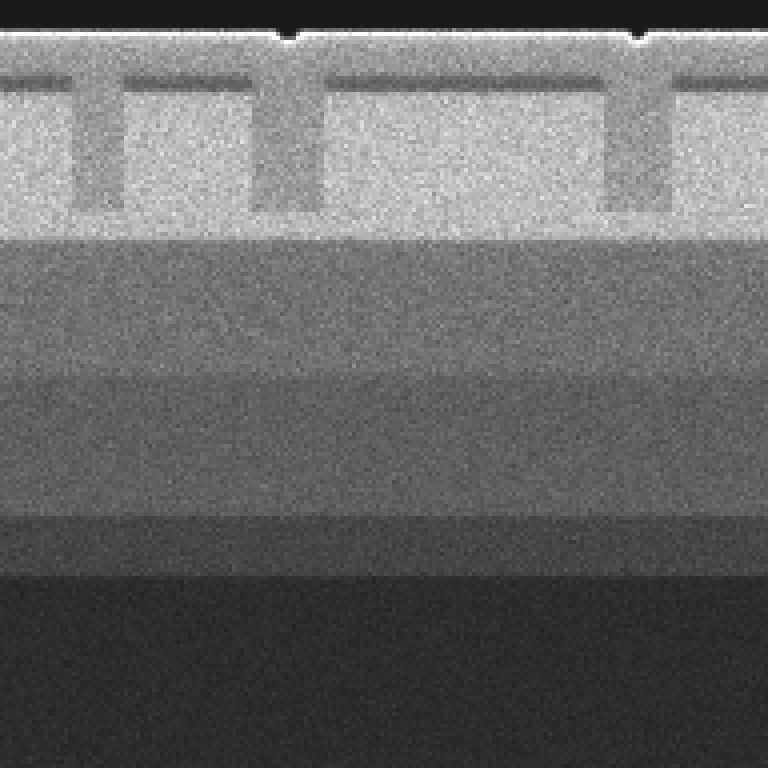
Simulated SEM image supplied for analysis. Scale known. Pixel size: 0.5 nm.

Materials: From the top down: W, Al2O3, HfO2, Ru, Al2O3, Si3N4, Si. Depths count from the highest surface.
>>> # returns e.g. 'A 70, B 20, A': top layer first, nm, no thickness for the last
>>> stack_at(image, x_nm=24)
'W 22, Al2O3 8, HfO2 74, Ru 68, Al2O3 70, Si3N4 30, Si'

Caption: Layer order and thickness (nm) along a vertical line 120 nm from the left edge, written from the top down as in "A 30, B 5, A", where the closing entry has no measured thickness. W 22, Al2O3 8, HfO2 74, Ru 68, Al2O3 70, Si3N4 30, Si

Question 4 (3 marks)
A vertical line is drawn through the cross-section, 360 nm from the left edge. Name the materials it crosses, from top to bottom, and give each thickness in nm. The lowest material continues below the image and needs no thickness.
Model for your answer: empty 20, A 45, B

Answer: W 22, Al2O3 8, HfO2 74, Ru 68, Al2O3 70, Si3N4 30, Si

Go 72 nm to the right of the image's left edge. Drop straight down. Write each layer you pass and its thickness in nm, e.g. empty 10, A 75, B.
W 22, Al2O3 8, HfO2 74, Ru 68, Al2O3 70, Si3N4 30, Si